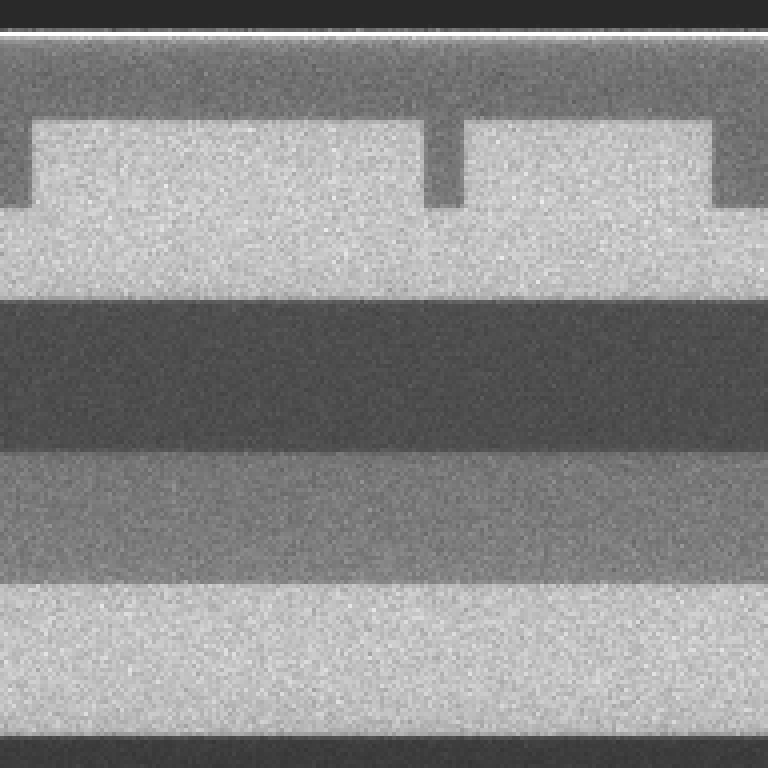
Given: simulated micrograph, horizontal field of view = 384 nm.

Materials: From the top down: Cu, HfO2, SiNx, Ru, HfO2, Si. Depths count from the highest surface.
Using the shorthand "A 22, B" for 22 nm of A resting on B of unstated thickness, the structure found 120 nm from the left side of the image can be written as Cu 44, HfO2 90, SiNx 76, Ru 66, HfO2 76, Si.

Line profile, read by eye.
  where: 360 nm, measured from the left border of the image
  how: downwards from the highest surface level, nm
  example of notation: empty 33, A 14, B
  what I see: Cu 88, HfO2 46, SiNx 76, Ru 66, HfO2 76, Si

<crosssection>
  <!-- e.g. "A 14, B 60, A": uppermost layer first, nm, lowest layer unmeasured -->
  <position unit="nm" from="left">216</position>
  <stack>Cu 88, HfO2 46, SiNx 76, Ru 66, HfO2 76, Si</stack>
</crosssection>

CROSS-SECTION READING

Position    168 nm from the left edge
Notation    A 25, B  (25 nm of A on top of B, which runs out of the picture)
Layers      Cu 44, HfO2 90, SiNx 76, Ru 66, HfO2 76, Si